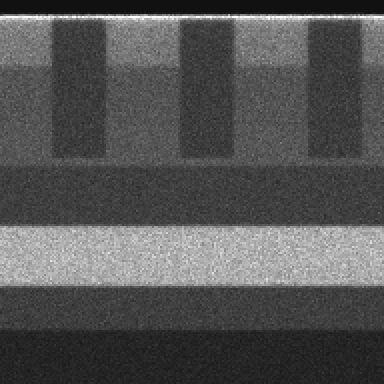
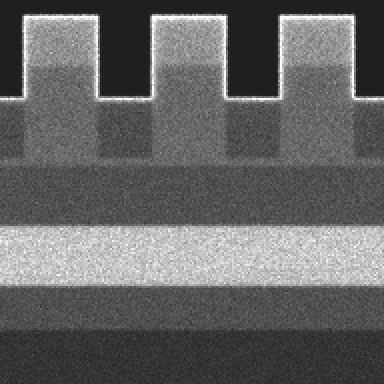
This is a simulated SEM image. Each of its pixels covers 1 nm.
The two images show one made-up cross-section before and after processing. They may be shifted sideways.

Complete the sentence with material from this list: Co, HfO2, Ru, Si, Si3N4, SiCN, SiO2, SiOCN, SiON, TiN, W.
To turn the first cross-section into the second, TiN must be removed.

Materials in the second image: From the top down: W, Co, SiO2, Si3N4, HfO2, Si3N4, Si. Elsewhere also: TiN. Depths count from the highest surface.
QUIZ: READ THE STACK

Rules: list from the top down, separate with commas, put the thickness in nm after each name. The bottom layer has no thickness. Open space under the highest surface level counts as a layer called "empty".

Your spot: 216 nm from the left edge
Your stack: W 50, Co 60, SiO2 40, Si3N4 60, HfO2 60, Si3N4 44, Si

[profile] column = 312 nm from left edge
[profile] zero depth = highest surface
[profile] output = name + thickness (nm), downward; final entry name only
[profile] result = W 50, Co 60, SiO2 40, Si3N4 60, HfO2 60, Si3N4 44, Si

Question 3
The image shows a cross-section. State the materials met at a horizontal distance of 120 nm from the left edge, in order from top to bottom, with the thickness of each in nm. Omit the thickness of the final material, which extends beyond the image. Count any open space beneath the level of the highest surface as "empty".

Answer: empty 82, TiN 60, SiO2 8, Si3N4 60, HfO2 60, Si3N4 44, Si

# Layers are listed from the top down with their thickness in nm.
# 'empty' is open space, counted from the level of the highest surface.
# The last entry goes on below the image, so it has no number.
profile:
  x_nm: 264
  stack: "empty 82, TiN 60, SiO2 8, Si3N4 60, HfO2 60, Si3N4 44, Si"